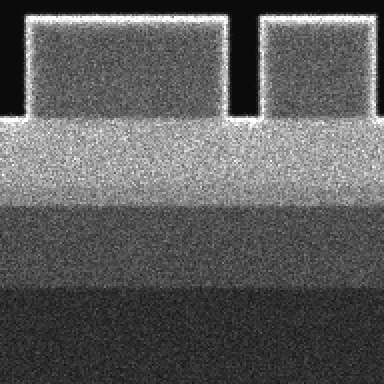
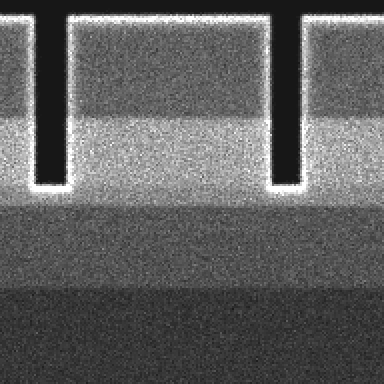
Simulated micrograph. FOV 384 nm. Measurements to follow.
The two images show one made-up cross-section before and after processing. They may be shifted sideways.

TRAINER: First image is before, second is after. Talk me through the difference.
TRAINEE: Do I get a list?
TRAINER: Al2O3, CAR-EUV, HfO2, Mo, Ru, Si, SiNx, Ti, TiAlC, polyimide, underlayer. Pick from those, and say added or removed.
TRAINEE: removed: Ru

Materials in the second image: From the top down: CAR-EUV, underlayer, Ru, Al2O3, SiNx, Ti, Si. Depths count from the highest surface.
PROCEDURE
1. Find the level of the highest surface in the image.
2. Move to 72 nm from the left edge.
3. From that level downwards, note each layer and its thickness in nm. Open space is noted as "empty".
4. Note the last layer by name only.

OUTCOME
CAR-EUV 60, underlayer 42, Ru 68, Al2O3 20, SiNx 28, Ti 54, Si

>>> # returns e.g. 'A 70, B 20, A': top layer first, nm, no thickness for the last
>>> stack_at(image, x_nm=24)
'CAR-EUV 60, underlayer 42, Ru 68, Al2O3 20, SiNx 28, Ti 54, Si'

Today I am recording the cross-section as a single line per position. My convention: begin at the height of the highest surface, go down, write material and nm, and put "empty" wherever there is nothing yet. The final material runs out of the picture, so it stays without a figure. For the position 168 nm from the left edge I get CAR-EUV 60, underlayer 42, Ru 68, Al2O3 20, SiNx 28, Ti 54, Si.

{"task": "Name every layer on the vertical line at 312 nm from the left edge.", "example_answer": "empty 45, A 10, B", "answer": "CAR-EUV 60, underlayer 42, Ru 68, Al2O3 20, SiNx 28, Ti 54, Si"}